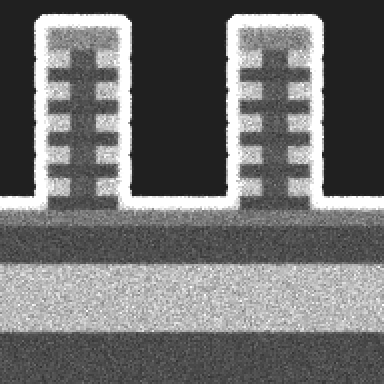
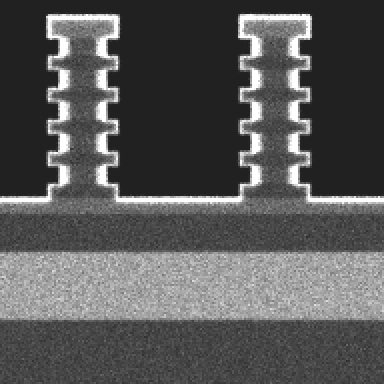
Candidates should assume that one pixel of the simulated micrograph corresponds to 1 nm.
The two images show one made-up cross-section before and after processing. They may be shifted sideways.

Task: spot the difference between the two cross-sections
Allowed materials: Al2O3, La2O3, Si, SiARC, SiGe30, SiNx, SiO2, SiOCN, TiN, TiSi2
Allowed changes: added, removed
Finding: removed Al2O3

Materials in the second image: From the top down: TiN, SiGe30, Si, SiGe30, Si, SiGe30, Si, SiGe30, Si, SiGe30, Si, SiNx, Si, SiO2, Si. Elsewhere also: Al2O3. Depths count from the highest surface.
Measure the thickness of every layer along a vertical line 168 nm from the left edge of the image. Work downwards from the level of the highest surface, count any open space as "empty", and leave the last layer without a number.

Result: empty 182, SiNx 16, Si 38, SiO2 68, Si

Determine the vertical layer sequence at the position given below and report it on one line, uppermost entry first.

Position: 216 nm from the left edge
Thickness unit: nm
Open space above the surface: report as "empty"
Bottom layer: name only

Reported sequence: empty 182, SiNx 16, Si 38, SiO2 68, Si